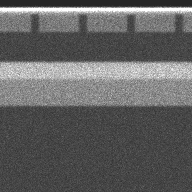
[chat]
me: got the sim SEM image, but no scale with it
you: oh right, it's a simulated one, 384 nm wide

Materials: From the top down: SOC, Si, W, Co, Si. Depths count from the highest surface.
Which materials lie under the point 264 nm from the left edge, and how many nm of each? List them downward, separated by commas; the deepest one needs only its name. SOC 12, Si 96, W 34, Co 54, Si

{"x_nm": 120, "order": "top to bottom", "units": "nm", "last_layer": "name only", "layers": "SOC 48, Si 60, W 34, Co 54, Si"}